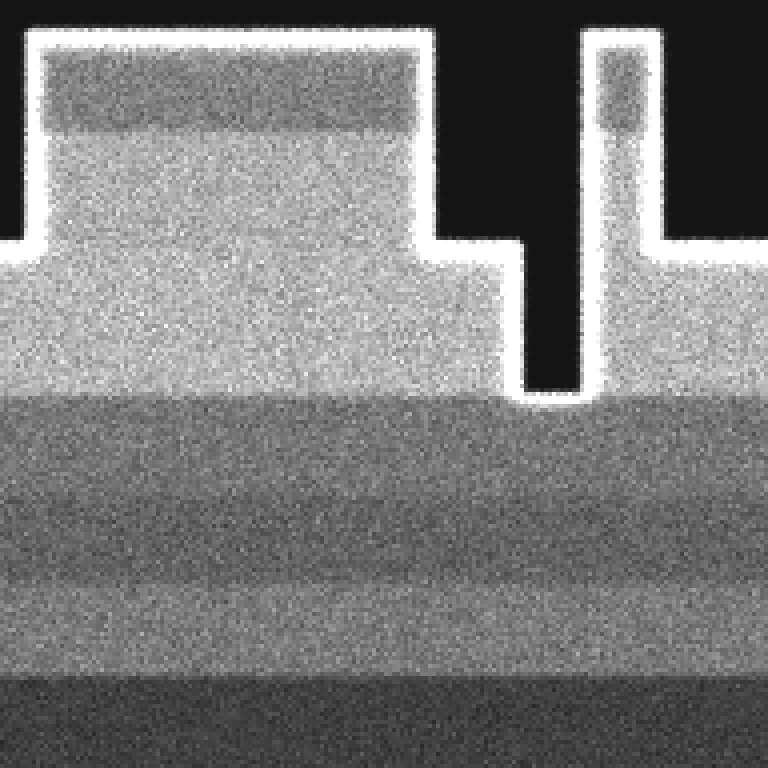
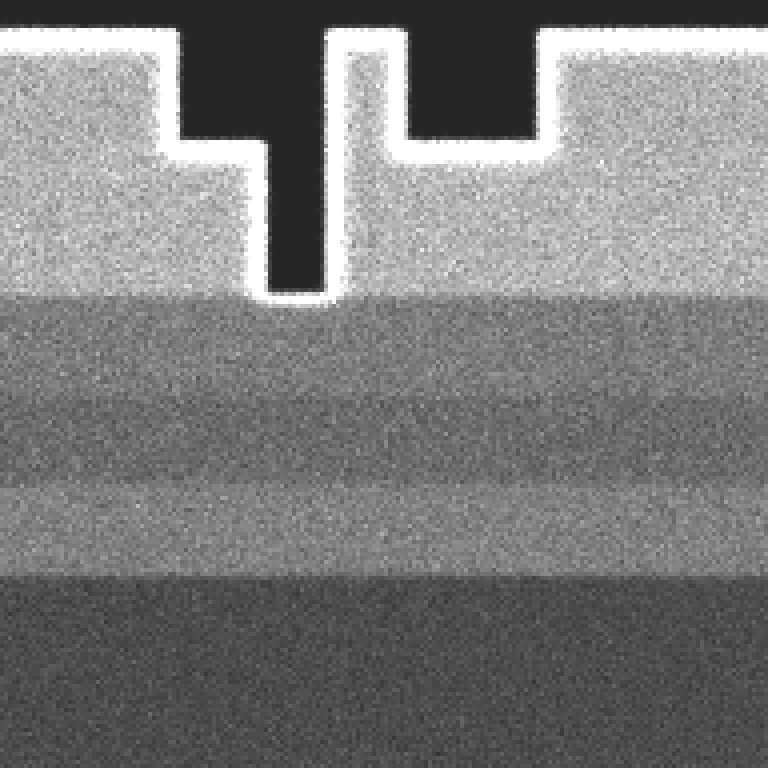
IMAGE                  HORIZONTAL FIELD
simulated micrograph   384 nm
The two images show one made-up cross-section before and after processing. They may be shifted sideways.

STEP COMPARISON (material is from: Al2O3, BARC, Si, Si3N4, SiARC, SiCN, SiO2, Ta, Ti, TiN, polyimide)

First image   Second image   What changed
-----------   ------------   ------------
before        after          SiARC, removed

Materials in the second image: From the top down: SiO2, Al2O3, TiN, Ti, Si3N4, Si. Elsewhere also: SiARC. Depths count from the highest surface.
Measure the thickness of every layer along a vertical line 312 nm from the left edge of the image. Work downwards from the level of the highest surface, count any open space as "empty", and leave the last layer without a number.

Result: SiO2 56, Al2O3 76, TiN 50, Ti 44, Si3N4 46, Si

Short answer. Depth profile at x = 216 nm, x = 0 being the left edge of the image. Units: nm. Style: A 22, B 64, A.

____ empty 56, Al2O3 76, TiN 50, Ti 44, Si3N4 46, Si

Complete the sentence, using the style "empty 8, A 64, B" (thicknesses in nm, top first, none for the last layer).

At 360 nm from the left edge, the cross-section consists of SiO2 56, Al2O3 76, TiN 50, Ti 44, Si3N4 46, Si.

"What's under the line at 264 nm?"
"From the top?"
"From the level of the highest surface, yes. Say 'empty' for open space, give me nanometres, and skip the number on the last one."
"empty 56, Al2O3 76, TiN 50, Ti 44, Si3N4 46, Si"